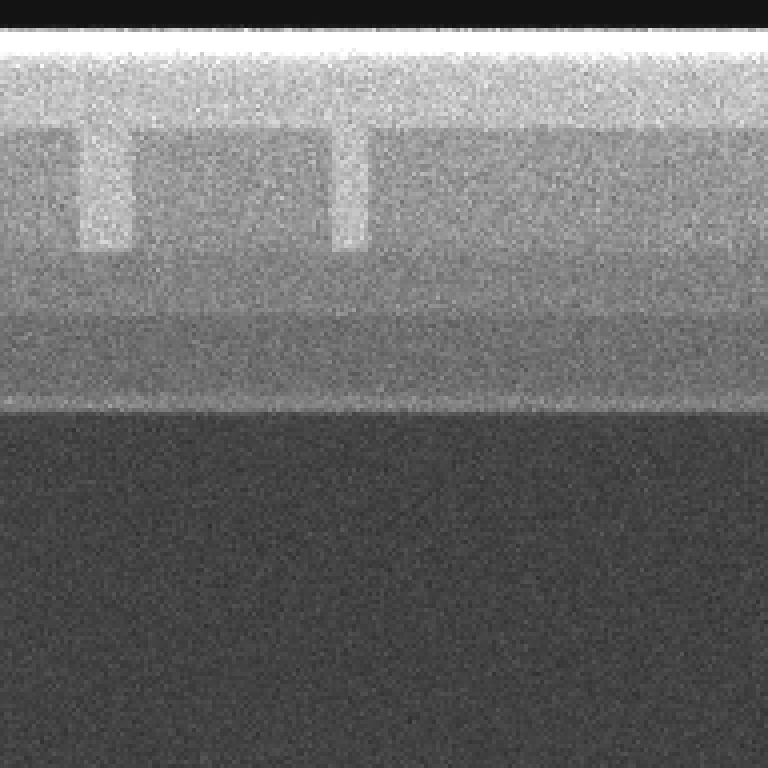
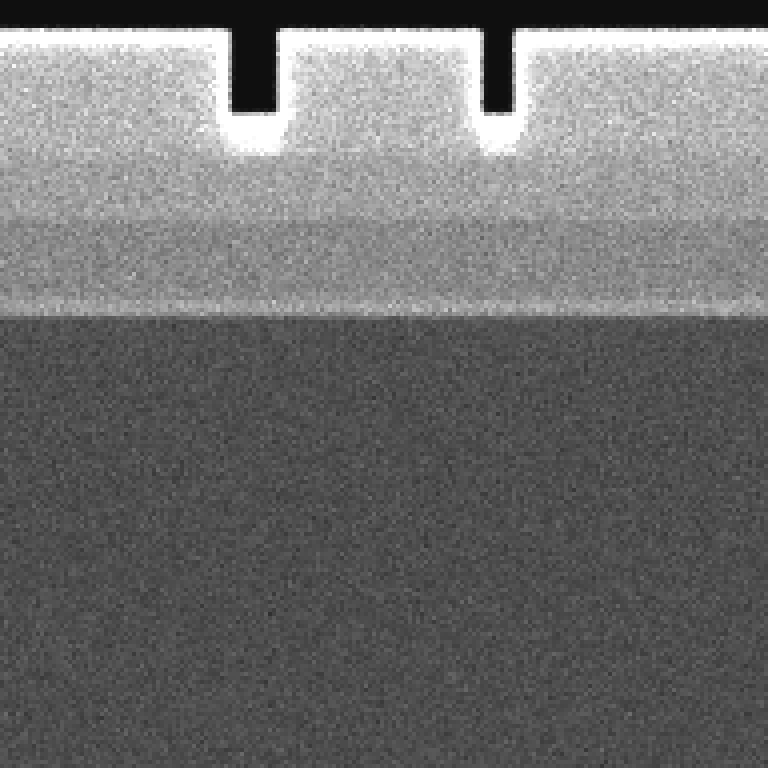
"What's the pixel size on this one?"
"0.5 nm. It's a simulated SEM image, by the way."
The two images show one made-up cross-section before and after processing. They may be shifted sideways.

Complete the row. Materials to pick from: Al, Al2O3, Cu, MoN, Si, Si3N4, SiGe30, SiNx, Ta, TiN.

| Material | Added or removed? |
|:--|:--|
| Al2O3 | removed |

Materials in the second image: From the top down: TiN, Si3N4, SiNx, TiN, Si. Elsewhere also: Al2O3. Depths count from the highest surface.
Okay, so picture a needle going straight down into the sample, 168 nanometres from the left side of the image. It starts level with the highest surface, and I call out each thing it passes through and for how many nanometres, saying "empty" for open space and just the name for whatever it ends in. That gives TiN 62, Si3N4 32, SiNx 40, TiN 8, Si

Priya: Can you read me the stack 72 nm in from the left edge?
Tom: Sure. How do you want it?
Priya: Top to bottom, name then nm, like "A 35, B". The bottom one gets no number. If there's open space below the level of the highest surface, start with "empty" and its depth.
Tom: TiN 62, Si3N4 32, SiNx 40, TiN 8, Si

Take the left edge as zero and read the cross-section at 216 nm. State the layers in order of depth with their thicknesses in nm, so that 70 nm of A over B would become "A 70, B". TiN 62, Si3N4 32, SiNx 40, TiN 8, Si